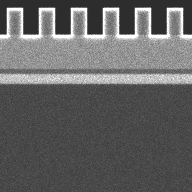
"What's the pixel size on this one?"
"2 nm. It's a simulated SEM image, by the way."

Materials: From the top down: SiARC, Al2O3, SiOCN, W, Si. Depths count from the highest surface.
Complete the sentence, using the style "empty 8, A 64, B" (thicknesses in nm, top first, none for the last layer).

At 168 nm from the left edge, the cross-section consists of SiARC 54, Al2O3 68, SiOCN 10, W 20, Si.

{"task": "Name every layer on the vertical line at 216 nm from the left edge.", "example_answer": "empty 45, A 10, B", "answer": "SiARC 54, Al2O3 68, SiOCN 10, W 20, Si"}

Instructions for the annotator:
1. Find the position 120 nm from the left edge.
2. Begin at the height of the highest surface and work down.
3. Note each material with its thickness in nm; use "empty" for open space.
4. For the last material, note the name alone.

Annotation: empty 54, Al2O3 68, SiOCN 10, W 20, Si